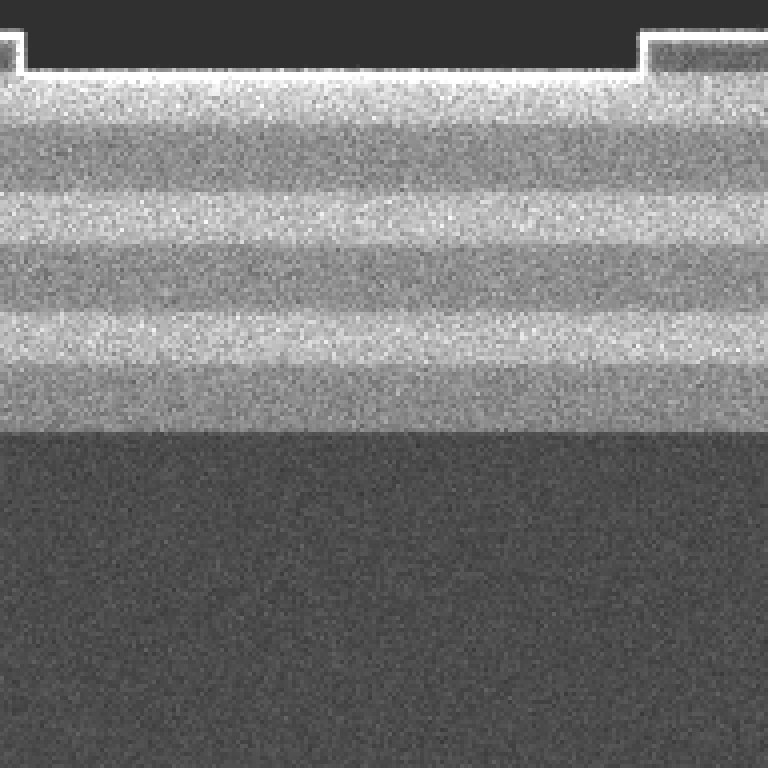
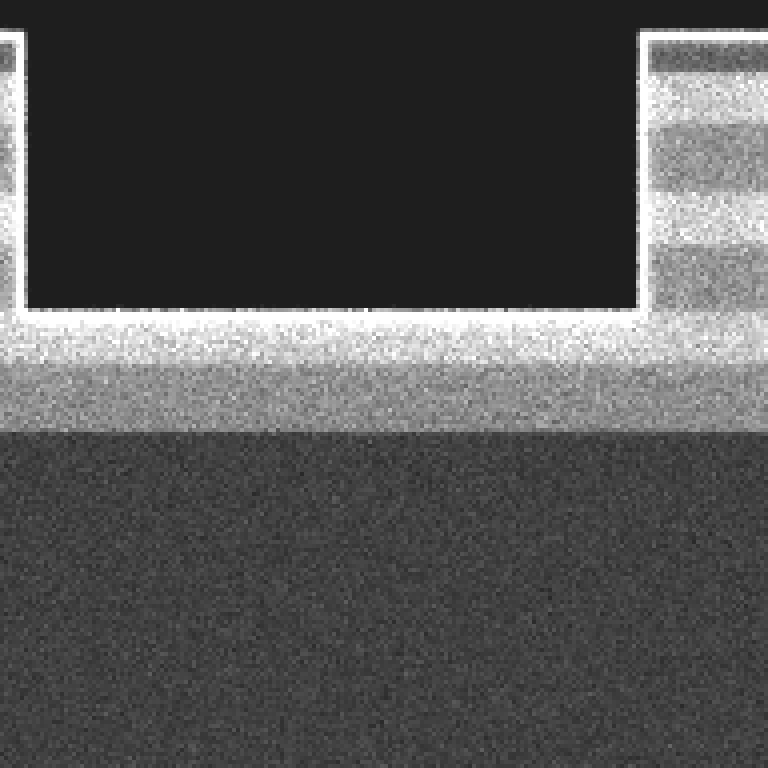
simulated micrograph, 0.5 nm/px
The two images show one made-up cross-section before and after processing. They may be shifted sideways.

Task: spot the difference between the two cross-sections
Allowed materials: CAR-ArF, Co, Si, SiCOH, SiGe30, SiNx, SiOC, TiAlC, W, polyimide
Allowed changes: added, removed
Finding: removed Co and W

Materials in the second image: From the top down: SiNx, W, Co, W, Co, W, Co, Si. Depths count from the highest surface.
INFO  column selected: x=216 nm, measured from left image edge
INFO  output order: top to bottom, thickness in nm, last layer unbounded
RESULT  empty 140, W 26, Co 34, Si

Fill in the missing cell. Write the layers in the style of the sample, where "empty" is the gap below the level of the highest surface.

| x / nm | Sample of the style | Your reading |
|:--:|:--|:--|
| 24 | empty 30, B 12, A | empty 140, W 26, Co 34, Si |